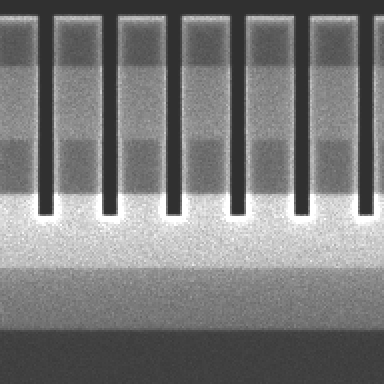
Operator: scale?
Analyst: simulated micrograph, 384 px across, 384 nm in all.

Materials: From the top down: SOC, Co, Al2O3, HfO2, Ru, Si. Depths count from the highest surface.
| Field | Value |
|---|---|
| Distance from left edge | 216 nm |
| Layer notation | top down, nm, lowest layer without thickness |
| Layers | SOC 50, Co 74, Al2O3 54, HfO2 74, Ru 62, Si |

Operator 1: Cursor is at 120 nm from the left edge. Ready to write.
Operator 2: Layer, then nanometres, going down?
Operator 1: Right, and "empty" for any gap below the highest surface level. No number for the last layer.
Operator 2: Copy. SOC 50, Co 74, Al2O3 54, HfO2 74, Ru 62, Si